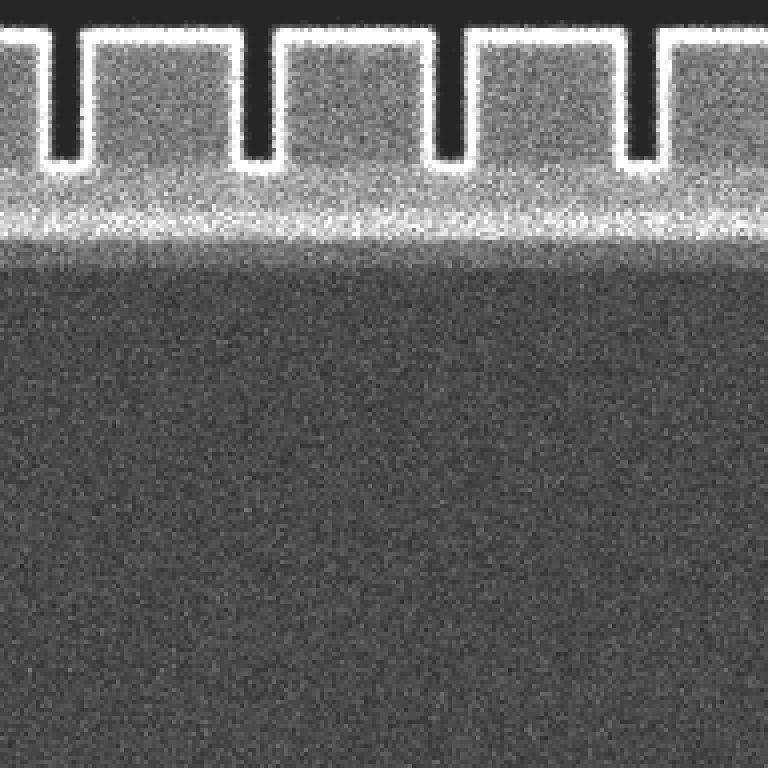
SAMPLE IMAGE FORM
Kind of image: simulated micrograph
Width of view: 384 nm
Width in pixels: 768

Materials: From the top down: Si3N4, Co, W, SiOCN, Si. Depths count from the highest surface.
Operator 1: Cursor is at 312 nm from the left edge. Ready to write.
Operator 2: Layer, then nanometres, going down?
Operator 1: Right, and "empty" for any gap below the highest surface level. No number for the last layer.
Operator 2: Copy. empty 66, Co 24, W 14, SiOCN 14, Si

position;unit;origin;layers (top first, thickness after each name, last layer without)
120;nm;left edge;empty 66, Co 24, W 14, SiOCN 14, Si